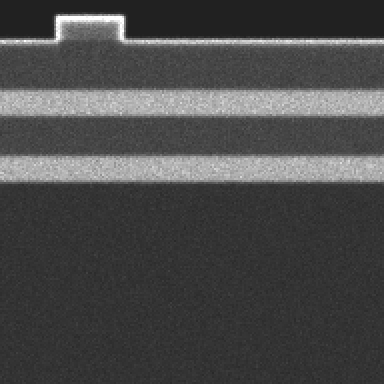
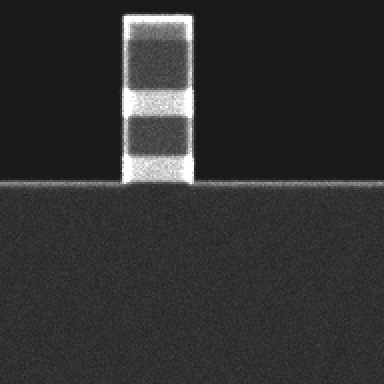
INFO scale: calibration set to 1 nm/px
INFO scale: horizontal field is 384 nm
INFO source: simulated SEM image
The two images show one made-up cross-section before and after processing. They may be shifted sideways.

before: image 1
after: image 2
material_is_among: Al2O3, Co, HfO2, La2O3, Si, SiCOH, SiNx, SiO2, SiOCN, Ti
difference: HfO2 and SiNx, removed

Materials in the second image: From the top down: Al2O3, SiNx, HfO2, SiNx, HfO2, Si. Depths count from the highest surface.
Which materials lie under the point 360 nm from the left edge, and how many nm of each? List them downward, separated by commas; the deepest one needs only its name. empty 166, Si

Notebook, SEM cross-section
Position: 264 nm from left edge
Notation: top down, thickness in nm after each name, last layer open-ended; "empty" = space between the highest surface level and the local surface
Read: empty 166, Si